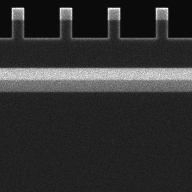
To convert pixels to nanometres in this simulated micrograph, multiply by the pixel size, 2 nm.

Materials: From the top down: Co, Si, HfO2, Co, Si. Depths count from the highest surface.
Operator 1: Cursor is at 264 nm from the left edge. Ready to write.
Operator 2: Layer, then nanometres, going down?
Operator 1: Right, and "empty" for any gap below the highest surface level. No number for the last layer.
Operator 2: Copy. empty 60, Si 60, HfO2 24, Co 24, Si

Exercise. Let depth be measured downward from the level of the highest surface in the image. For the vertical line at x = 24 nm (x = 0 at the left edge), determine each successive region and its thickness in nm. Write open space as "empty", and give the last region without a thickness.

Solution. Co 24, Si 96, HfO2 24, Co 24, Si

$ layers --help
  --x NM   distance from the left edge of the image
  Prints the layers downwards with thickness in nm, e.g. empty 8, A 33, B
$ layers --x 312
Co 24, Si 96, HfO2 24, Co 24, Si